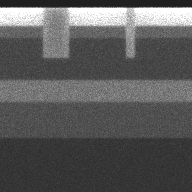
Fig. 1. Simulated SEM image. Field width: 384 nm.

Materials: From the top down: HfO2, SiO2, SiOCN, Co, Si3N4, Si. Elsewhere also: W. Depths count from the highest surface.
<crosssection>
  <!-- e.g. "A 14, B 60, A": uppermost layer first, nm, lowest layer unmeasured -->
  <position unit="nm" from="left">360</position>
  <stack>HfO2 36, SiO2 24, SiOCN 84, Co 44, Si3N4 72, Si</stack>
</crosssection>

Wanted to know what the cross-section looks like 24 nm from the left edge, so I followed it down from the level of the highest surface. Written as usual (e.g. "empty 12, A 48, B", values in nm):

HfO2 36, SiO2 24, SiOCN 84, Co 44, Si3N4 72, Si